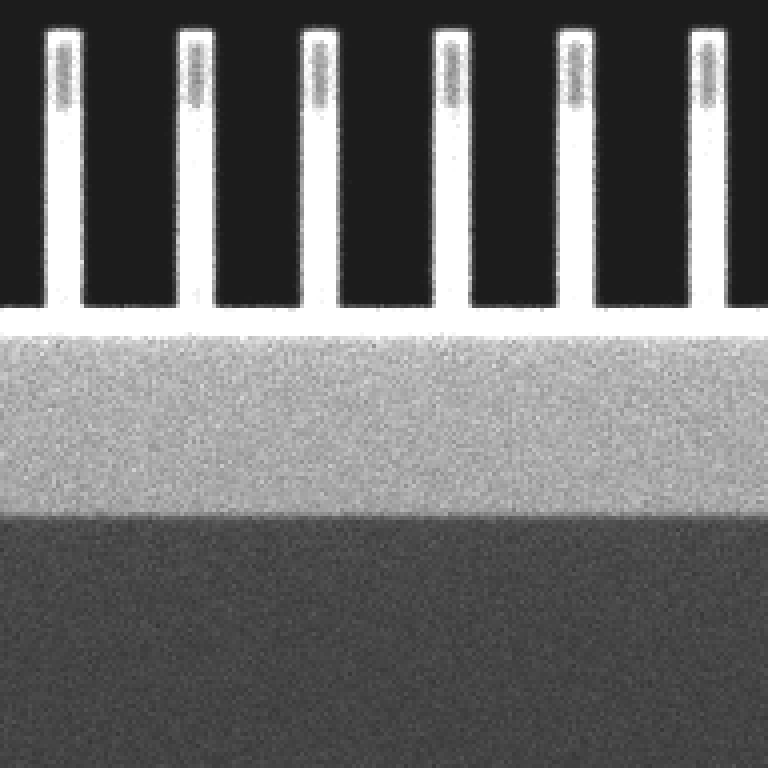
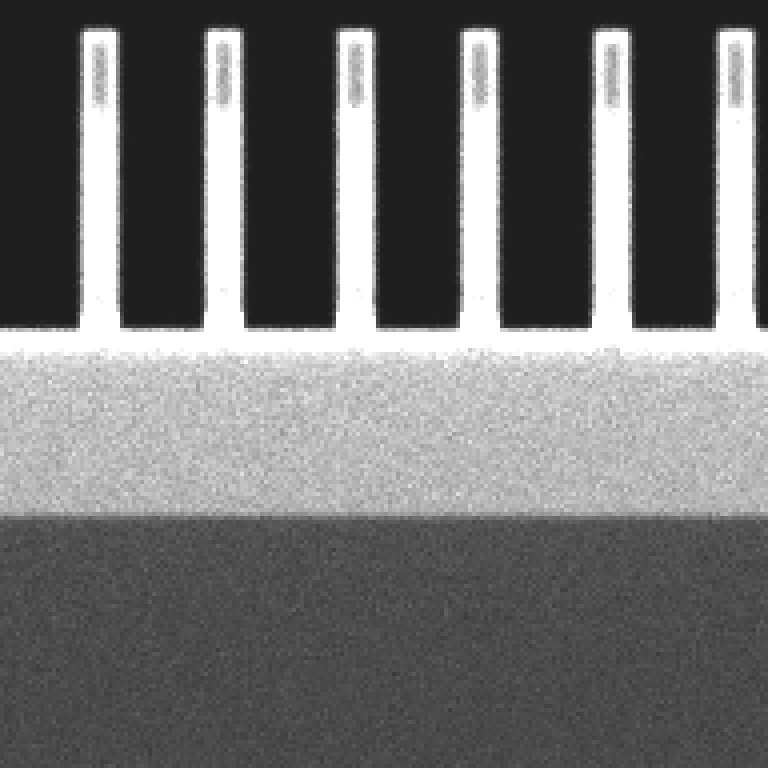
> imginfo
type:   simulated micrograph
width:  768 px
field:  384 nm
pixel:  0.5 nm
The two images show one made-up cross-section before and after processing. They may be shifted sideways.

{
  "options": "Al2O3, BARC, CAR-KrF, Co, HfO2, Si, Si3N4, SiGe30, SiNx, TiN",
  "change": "removed",
  "material": "HfO2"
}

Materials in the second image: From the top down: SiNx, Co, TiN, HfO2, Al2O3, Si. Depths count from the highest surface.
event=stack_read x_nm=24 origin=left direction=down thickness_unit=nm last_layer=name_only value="empty 150, Al2O3 92, Si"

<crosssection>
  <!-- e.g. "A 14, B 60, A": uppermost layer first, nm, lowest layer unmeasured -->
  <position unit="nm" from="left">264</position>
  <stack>empty 150, Al2O3 92, Si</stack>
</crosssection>